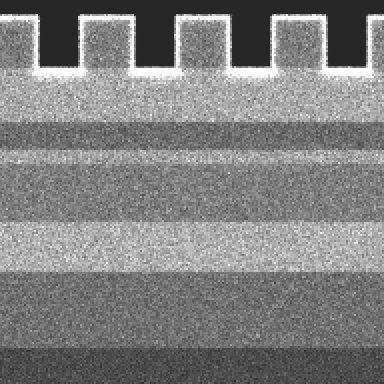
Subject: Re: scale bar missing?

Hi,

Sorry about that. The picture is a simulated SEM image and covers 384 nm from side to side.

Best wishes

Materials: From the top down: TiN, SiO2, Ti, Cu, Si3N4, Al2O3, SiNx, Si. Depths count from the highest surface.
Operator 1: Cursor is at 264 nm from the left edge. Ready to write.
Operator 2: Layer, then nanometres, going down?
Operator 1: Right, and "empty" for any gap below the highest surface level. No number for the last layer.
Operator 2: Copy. empty 52, SiO2 54, Ti 28, Cu 14, Si3N4 58, Al2O3 50, SiNx 76, Si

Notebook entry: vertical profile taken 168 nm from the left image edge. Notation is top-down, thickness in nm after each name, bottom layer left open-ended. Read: empty 52, SiO2 54, Ti 28, Cu 14, Si3N4 58, Al2O3 50, SiNx 76, Si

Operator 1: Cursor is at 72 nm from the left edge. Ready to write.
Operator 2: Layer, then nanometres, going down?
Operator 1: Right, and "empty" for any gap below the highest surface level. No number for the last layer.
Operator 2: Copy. empty 52, SiO2 54, Ti 28, Cu 14, Si3N4 58, Al2O3 50, SiNx 76, Si